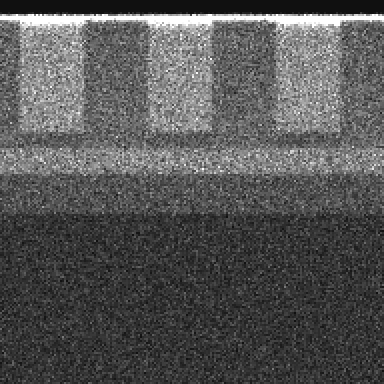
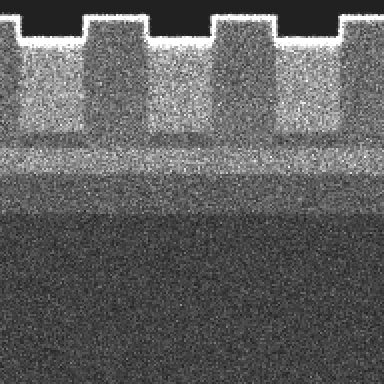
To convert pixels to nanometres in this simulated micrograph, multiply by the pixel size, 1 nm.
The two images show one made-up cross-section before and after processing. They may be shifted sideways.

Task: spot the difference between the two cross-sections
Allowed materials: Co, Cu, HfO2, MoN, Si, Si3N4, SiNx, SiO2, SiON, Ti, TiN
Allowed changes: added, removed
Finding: removed SiO2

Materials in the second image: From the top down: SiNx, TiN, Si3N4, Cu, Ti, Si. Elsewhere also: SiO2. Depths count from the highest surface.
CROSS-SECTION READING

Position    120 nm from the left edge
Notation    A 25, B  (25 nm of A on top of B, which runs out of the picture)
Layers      SiNx 16, TiN 62, Si3N4 54, Cu 26, Ti 40, Si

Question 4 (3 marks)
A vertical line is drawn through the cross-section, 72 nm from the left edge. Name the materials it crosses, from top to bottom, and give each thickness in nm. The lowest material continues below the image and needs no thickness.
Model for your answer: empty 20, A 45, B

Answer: empty 22, SiO2 94, SiNx 16, Cu 26, Ti 40, Si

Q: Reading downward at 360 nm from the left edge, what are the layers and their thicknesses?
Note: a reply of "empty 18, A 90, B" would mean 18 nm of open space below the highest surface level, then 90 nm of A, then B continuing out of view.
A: SiNx 16, TiN 62, Si3N4 54, Cu 26, Ti 40, Si